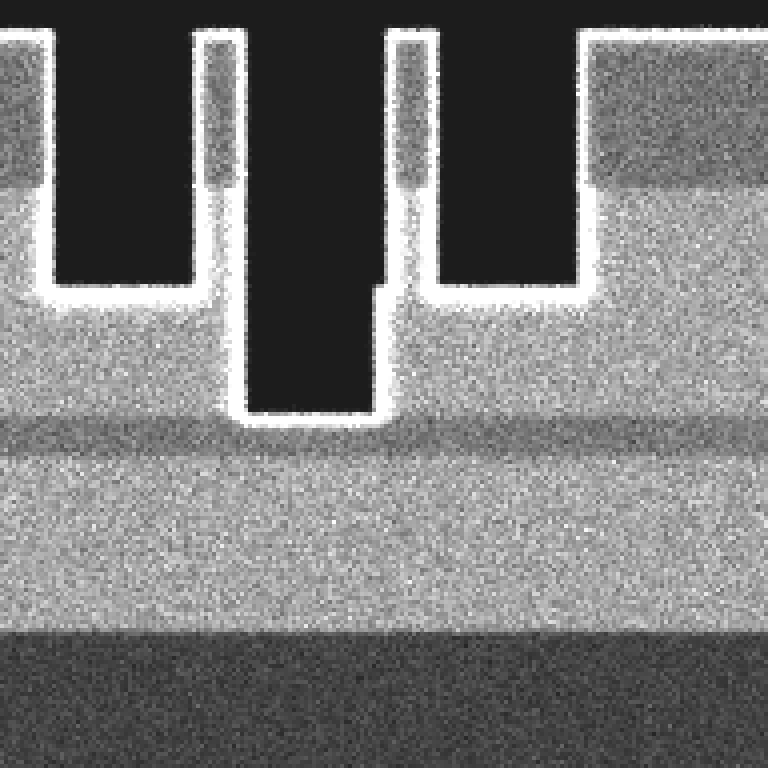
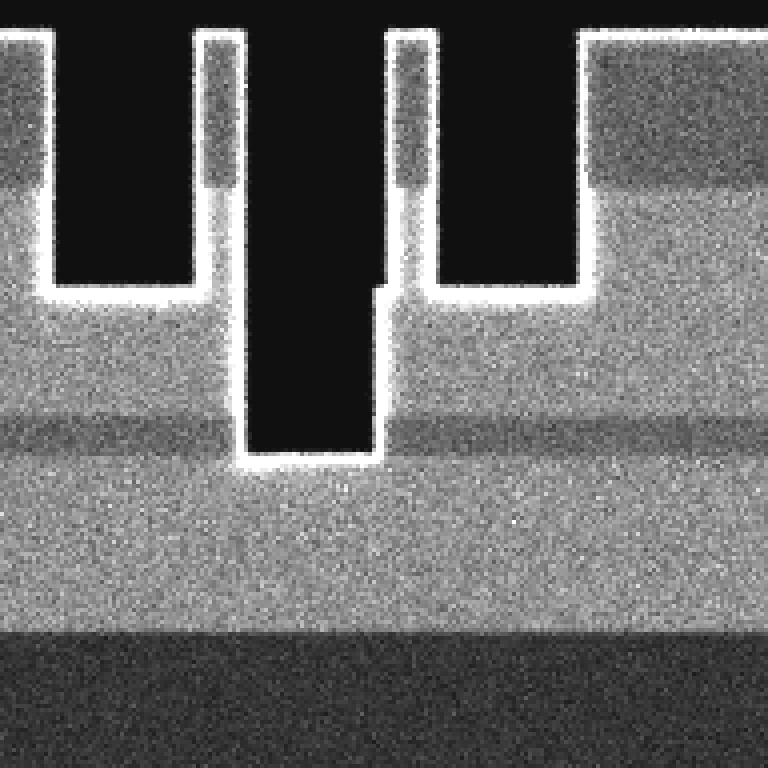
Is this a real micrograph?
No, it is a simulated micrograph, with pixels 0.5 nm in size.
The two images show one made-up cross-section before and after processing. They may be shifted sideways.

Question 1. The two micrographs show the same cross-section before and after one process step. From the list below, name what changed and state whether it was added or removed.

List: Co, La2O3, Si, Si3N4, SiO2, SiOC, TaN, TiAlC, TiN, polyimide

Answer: Si3N4, removed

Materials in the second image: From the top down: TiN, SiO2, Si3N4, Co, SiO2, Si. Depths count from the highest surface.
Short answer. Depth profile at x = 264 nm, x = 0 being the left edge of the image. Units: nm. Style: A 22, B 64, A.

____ empty 128, SiO2 64, Si3N4 20, Co 50, SiO2 38, Si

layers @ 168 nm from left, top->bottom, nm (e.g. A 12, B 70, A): empty 212, Co 50, SiO2 38, Si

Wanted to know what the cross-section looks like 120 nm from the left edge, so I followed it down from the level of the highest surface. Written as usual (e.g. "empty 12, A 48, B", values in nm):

TiN 78, SiO2 114, Si3N4 20, SiO2 88, Si